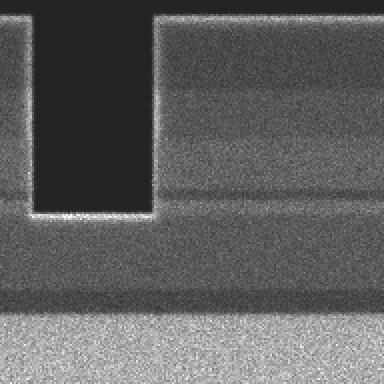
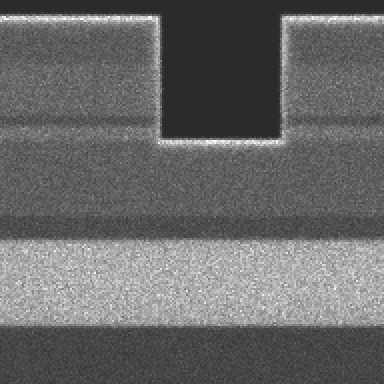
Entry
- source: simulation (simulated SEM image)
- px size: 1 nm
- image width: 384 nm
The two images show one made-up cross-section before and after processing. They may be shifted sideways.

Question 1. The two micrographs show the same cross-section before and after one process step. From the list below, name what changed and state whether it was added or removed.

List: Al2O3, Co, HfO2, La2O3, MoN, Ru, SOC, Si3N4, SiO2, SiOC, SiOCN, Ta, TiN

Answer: SOC, removed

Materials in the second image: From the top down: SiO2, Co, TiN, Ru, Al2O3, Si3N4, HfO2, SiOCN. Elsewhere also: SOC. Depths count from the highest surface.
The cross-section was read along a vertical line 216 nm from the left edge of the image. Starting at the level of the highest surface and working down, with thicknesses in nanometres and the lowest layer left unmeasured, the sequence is empty 124, Al2O3 76, Si3N4 24, HfO2 86, SiOCN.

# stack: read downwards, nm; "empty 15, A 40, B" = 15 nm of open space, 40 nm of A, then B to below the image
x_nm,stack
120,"SiO2 48, Co 52, TiN 10, Ru 14, Al2O3 76, Si3N4 24, HfO2 86, SiOCN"